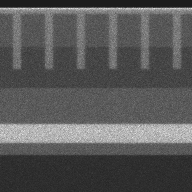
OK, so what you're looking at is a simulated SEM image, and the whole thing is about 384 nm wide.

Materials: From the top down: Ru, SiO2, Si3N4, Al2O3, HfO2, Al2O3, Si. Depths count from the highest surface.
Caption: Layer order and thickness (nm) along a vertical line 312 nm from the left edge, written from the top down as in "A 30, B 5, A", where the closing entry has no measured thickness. Ru 12, SiO2 66, Si3N4 82, Al2O3 72, HfO2 38, Al2O3 24, Si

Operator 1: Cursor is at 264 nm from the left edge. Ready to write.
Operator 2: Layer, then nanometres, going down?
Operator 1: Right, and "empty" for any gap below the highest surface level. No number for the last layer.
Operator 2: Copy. Ru 12, SiO2 66, Si3N4 82, Al2O3 72, HfO2 38, Al2O3 24, Si